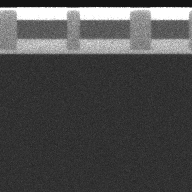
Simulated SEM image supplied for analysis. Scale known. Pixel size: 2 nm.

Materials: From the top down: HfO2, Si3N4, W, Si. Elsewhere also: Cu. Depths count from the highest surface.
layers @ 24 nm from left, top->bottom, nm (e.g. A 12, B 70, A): Cu 84, W 8, Si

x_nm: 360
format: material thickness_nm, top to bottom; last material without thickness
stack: HfO2 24, Si3N4 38, W 30, Si